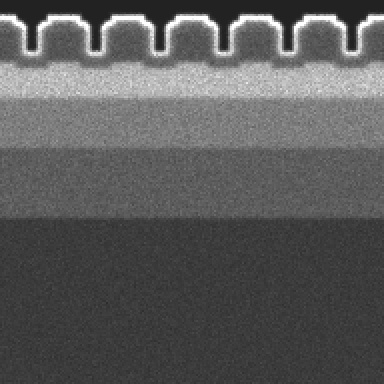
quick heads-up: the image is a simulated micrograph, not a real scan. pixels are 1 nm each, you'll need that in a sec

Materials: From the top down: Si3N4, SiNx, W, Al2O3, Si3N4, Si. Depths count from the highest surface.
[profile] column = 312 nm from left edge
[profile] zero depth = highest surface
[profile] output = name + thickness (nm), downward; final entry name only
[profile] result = Si3N4 16, SiNx 30, W 36, Al2O3 50, Si3N4 70, Si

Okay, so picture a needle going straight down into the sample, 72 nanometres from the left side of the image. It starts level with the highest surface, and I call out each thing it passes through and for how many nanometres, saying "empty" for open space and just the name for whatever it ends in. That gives Si3N4 16, SiNx 30, W 36, Al2O3 50, Si3N4 70, Si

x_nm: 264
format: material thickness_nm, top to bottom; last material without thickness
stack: Si3N4 16, SiNx 30, W 36, Al2O3 50, Si3N4 70, Si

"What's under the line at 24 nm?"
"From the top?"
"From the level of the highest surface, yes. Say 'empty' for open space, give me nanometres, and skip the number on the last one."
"empty 10, Si3N4 42, W 30, Al2O3 50, Si3N4 70, Si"